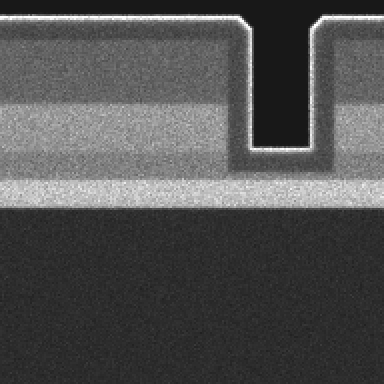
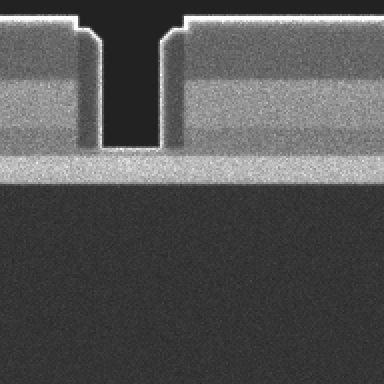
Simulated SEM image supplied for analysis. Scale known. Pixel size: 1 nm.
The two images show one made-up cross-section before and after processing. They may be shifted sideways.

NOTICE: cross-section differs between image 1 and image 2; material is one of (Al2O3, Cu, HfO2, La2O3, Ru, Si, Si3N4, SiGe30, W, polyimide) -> removed: Si3N4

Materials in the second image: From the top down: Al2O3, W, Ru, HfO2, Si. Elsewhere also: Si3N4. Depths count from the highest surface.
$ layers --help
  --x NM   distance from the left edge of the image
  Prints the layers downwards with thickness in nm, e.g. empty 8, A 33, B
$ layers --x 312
Al2O3 64, W 48, Ru 28, HfO2 28, Si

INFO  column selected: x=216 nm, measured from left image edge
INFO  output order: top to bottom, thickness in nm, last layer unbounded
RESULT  Al2O3 64, W 48, Ru 28, HfO2 28, Si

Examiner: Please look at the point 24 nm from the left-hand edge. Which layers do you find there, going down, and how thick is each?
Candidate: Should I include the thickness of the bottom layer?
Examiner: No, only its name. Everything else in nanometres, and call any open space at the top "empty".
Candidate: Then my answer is Al2O3 64, W 48, Ru 28, HfO2 28, Si